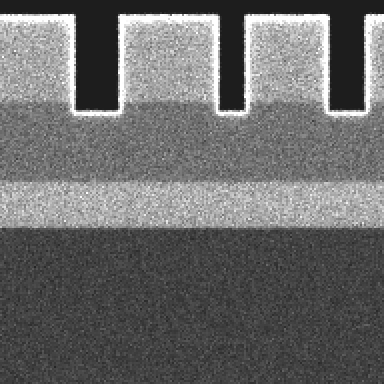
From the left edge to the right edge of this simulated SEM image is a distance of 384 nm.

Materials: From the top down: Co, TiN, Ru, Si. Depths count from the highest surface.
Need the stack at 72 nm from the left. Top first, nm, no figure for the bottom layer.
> Co 86, TiN 80, Ru 46, Si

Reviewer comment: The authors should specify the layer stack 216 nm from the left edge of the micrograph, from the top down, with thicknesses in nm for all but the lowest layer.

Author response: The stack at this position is Co 86, TiN 80, Ru 46, Si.